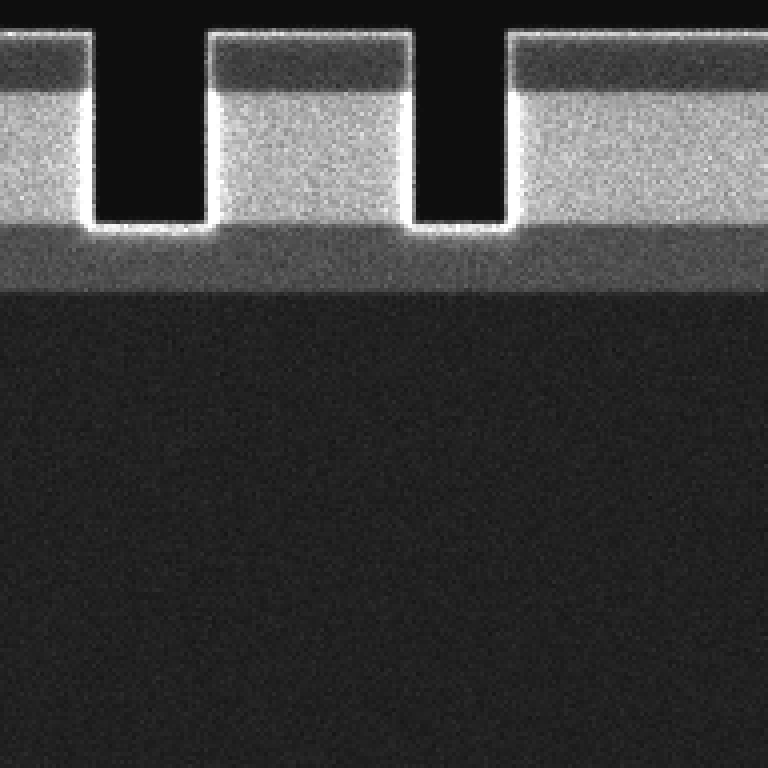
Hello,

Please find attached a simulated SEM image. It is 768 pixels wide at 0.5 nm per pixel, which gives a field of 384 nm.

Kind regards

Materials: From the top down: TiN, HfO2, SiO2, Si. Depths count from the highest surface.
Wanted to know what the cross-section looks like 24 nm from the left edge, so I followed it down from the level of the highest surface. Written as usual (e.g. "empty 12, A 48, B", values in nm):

TiN 30, HfO2 66, SiO2 34, Si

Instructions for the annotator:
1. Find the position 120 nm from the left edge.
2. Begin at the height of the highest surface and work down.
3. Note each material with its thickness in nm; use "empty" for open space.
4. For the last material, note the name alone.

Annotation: TiN 30, HfO2 66, SiO2 34, Si